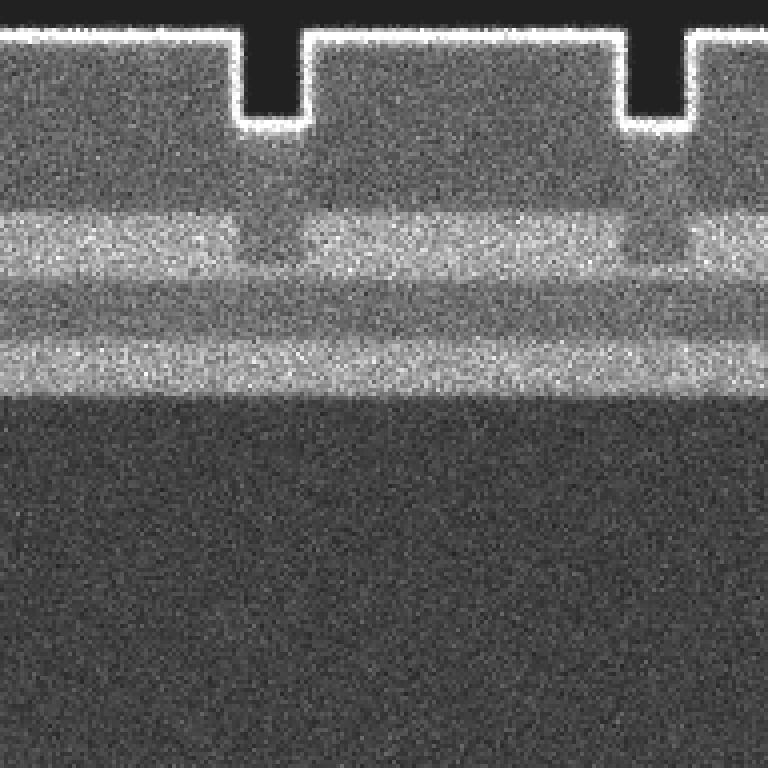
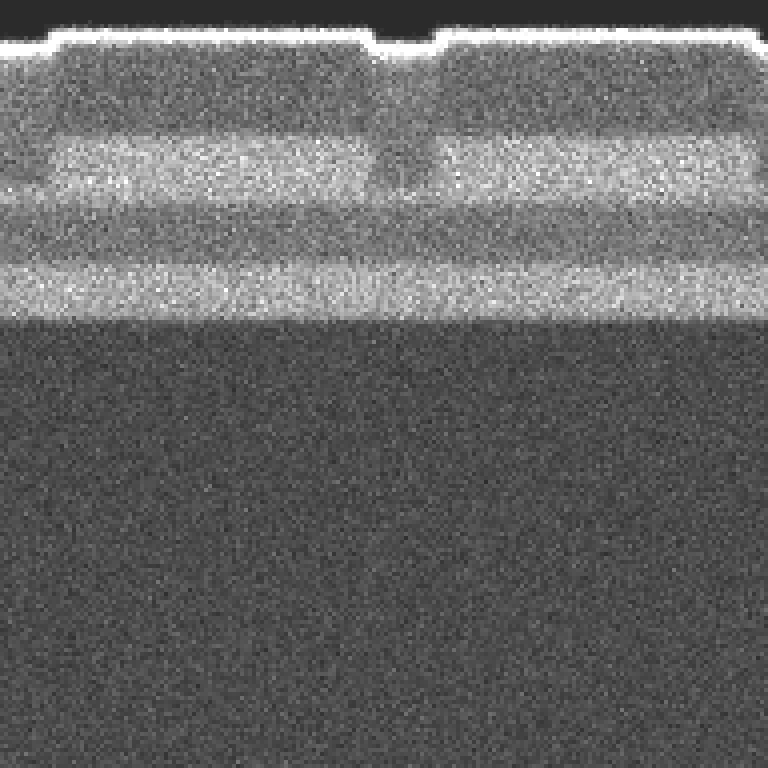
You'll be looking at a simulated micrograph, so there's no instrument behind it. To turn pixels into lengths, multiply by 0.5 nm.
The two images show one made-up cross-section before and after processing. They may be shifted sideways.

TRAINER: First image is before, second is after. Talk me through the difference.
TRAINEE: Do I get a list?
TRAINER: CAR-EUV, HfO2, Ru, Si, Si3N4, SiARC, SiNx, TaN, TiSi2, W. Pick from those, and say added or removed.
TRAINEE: removed: SiNx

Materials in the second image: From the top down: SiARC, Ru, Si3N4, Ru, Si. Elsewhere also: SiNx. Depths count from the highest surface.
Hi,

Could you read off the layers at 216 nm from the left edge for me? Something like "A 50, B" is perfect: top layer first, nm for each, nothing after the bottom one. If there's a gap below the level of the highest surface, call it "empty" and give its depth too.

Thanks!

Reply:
empty 6, SiARC 72, Ru 8, Si3N4 30, Ru 28, Si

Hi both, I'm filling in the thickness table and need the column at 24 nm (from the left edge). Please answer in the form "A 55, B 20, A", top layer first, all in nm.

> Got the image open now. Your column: empty 6, SiARC 72, Ru 8, Si3N4 30, Ru 28, Si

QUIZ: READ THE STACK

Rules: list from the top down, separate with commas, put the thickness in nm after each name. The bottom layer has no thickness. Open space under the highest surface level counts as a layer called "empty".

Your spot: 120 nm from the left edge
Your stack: SiNx 52, Ru 34, Si3N4 30, Ru 28, Si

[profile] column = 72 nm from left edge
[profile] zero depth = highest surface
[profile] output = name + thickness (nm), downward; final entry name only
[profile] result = SiNx 52, Ru 34, Si3N4 30, Ru 28, Si